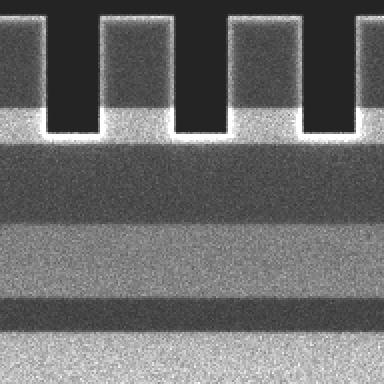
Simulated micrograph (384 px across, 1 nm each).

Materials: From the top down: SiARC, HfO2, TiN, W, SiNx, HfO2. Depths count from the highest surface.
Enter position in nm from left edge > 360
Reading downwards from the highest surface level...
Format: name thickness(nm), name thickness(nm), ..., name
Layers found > SiARC 92, HfO2 36, TiN 80, W 74, SiNx 34, HfO2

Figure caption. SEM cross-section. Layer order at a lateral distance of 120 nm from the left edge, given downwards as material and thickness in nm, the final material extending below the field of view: SiARC 92, HfO2 36, TiN 80, W 74, SiNx 34, HfO2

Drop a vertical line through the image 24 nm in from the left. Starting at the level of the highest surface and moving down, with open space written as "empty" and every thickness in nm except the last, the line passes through SiARC 92, HfO2 36, TiN 80, W 74, SiNx 34, HfO2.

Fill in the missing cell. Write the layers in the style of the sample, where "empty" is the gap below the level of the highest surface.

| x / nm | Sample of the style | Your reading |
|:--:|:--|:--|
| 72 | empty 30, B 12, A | empty 118, HfO2 10, TiN 80, W 74, SiNx 34, HfO2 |